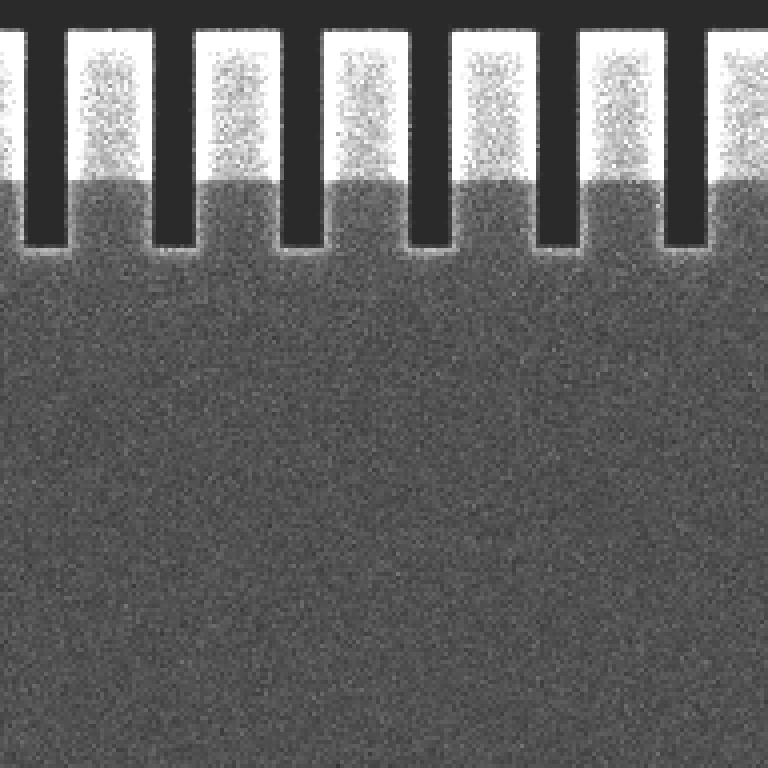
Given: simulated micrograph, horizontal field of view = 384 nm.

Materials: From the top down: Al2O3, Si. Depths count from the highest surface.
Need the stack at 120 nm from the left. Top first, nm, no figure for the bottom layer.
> Al2O3 74, Si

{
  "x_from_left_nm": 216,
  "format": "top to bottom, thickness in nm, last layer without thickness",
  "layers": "empty 108, Si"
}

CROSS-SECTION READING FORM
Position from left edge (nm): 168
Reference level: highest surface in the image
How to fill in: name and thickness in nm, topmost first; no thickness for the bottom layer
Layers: Al2O3 74, Si